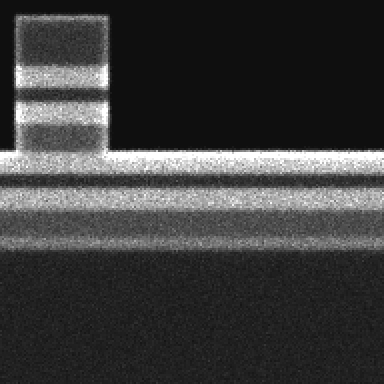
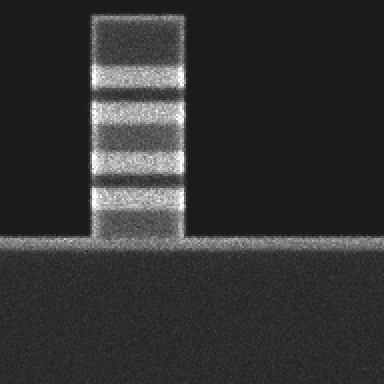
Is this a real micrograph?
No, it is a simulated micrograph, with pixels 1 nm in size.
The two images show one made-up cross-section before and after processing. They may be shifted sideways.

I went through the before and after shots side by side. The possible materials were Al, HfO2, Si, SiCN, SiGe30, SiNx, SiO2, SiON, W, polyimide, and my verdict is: removed, HfO2 and Si and SiO2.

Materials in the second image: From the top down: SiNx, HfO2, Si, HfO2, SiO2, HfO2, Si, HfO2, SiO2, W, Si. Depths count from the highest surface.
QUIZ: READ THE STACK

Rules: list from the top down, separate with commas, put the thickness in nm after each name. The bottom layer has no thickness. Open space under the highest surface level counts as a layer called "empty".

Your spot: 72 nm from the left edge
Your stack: empty 222, W 12, Si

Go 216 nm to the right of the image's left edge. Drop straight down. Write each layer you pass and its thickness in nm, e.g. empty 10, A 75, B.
empty 222, W 12, Si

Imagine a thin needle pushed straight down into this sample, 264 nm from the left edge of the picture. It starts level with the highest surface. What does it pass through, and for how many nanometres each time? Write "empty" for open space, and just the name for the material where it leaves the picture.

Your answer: empty 222, W 12, Si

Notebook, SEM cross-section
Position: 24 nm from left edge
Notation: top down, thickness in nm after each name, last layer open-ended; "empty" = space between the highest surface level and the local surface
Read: empty 222, W 12, Si